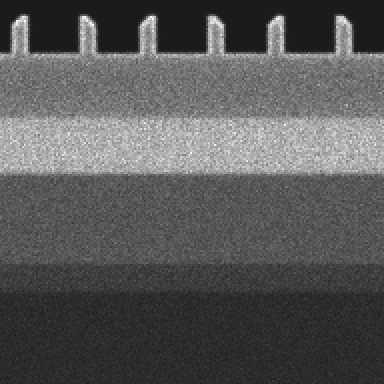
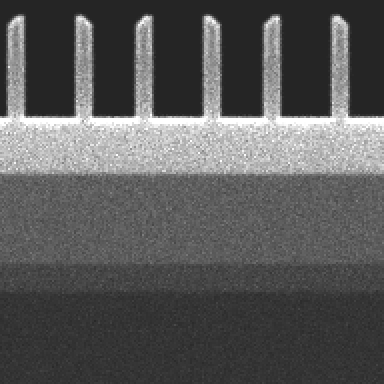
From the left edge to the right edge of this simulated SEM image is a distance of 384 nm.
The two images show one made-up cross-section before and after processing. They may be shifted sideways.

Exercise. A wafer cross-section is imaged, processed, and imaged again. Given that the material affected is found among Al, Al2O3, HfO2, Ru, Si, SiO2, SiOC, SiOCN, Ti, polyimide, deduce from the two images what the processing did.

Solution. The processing removed Ru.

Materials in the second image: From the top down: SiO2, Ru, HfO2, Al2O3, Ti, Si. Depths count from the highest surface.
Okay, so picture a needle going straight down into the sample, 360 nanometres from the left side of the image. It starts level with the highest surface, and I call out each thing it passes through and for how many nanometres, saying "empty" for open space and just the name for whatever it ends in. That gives empty 102, HfO2 56, Al2O3 90, Ti 28, Si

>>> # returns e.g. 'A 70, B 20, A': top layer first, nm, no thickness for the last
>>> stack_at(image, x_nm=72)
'empty 102, HfO2 56, Al2O3 90, Ti 28, Si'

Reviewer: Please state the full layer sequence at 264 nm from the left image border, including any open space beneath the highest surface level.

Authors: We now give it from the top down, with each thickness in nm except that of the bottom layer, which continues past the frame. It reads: empty 8, SiO2 30, Ru 64, HfO2 56, Al2O3 90, Ti 28, Si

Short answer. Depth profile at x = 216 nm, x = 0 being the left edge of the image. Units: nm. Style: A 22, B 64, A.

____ empty 6, SiO2 32, Ru 64, HfO2 56, Al2O3 90, Ti 28, Si